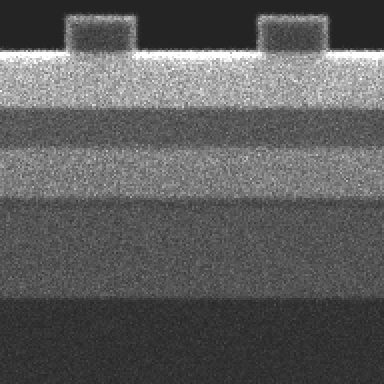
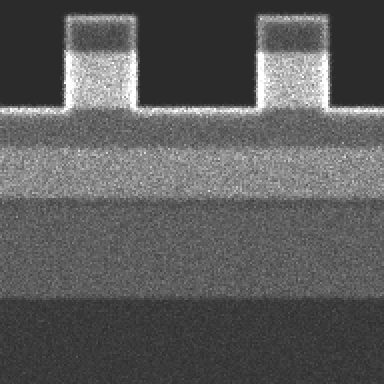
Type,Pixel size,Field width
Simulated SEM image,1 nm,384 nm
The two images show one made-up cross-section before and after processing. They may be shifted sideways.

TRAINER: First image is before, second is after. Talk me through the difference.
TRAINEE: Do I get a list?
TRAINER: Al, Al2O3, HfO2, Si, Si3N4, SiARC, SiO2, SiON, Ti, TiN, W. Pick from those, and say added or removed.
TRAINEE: removed: HfO2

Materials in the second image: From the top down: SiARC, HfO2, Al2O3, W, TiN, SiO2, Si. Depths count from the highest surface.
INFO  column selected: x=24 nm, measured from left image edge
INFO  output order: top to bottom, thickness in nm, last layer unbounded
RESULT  empty 92, Al2O3 40, W 50, TiN 10, SiO2 90, Si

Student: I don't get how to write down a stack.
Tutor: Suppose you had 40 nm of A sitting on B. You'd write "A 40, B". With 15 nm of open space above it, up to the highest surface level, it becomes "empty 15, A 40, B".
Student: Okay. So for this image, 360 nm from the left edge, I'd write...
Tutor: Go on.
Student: empty 92, Al2O3 40, W 50, TiN 10, SiO2 90, Si